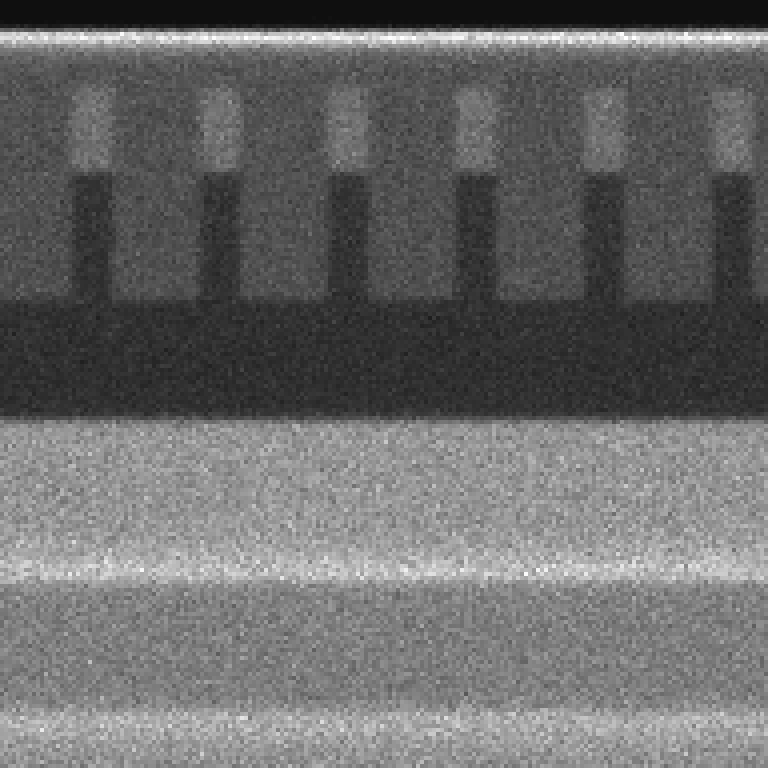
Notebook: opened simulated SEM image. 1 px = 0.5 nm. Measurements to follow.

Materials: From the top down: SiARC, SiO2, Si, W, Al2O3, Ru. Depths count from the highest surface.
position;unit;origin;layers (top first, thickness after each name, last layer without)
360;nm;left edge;SiARC 28, SiO2 42, Si 124, W 80, Al2O3 66, Ru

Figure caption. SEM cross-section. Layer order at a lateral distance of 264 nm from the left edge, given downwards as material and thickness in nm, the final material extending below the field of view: SiARC 134, Si 60, W 80, Al2O3 66, Ru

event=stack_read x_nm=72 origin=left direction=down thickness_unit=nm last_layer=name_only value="SiARC 134, Si 60, W 80, Al2O3 66, Ru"